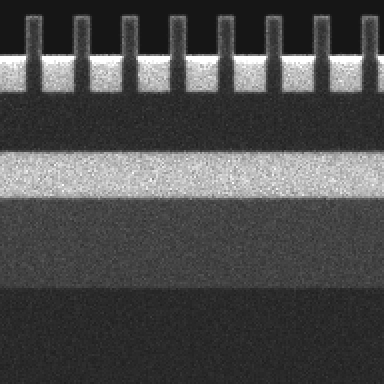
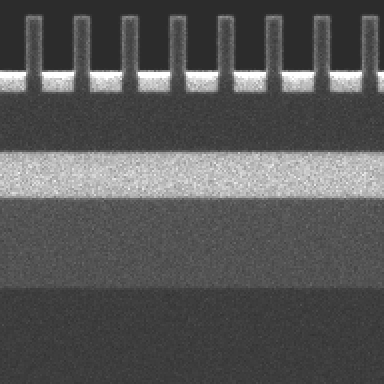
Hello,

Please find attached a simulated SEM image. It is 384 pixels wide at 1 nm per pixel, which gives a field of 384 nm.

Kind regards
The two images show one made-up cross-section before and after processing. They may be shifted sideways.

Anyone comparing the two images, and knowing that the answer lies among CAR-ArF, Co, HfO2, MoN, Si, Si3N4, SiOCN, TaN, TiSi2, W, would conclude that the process removed HfO2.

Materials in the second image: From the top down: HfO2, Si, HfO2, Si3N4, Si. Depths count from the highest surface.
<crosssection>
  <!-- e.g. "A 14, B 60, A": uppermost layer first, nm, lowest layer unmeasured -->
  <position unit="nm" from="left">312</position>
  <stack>empty 56, HfO2 20, Si 60, HfO2 46, Si3N4 90, Si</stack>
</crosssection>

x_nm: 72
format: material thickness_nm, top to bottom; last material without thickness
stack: empty 56, HfO2 20, Si 60, HfO2 46, Si3N4 90, Si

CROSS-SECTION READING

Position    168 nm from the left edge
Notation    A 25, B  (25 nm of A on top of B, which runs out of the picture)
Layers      empty 56, HfO2 20, Si 60, HfO2 46, Si3N4 90, Si